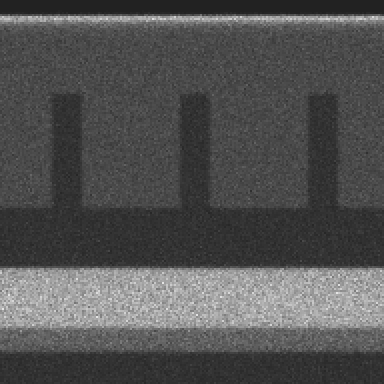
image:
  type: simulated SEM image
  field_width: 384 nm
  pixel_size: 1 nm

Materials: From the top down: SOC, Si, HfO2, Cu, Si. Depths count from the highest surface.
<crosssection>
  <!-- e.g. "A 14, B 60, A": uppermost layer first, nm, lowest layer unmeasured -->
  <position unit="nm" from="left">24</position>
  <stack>SOC 192, Si 60, HfO2 60, Cu 24, Si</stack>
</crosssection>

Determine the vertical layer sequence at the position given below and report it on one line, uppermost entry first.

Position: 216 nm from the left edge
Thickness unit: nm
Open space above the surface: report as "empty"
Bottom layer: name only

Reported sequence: SOC 192, Si 60, HfO2 60, Cu 24, Si